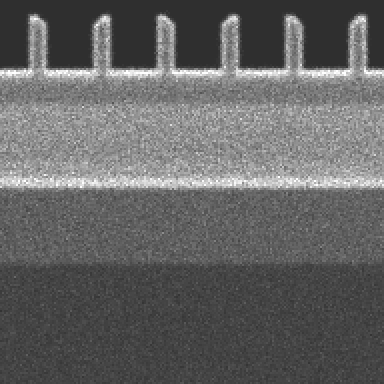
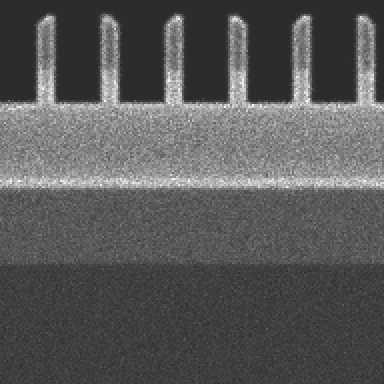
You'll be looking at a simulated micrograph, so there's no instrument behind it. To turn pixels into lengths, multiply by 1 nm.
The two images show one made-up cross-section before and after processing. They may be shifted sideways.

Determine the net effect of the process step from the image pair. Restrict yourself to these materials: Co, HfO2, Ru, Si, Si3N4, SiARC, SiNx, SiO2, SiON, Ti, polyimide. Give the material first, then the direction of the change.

SiO2: removed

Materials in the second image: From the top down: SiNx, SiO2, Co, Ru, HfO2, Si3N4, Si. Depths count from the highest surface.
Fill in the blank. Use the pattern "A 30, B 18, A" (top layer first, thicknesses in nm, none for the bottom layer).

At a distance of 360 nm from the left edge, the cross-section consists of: SiNx 54, SiO2 34, Co 58, Ru 16, HfO2 10, Si3N4 76, Si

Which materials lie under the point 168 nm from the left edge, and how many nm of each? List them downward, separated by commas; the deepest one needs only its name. empty 6, SiNx 48, SiO2 34, Co 58, Ru 16, HfO2 10, Si3N4 76, Si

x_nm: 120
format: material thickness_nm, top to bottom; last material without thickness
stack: empty 88, Co 58, Ru 16, HfO2 10, Si3N4 76, Si